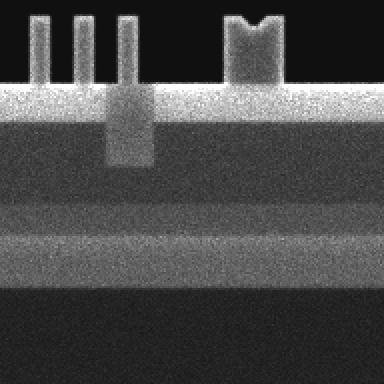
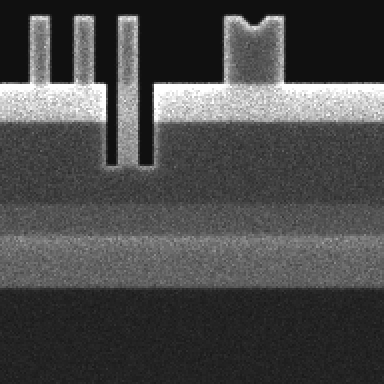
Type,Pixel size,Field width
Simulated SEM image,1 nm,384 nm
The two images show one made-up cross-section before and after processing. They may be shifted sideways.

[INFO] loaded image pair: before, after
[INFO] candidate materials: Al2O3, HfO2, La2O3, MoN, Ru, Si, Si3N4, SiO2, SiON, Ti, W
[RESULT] removed Ru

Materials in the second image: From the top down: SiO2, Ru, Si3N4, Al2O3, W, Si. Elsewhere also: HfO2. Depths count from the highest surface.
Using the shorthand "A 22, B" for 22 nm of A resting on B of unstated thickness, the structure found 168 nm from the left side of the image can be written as empty 68, HfO2 38, Si3N4 82, Al2O3 32, W 52, Si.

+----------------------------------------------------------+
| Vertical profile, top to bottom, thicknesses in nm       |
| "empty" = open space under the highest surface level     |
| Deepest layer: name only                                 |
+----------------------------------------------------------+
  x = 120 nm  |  SiO2 68, Ru 82, Si3N4 38, Al2O3 32, W 52, Si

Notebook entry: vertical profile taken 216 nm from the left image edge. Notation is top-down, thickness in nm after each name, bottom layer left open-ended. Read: empty 68, HfO2 38, Si3N4 82, Al2O3 32, W 52, Si